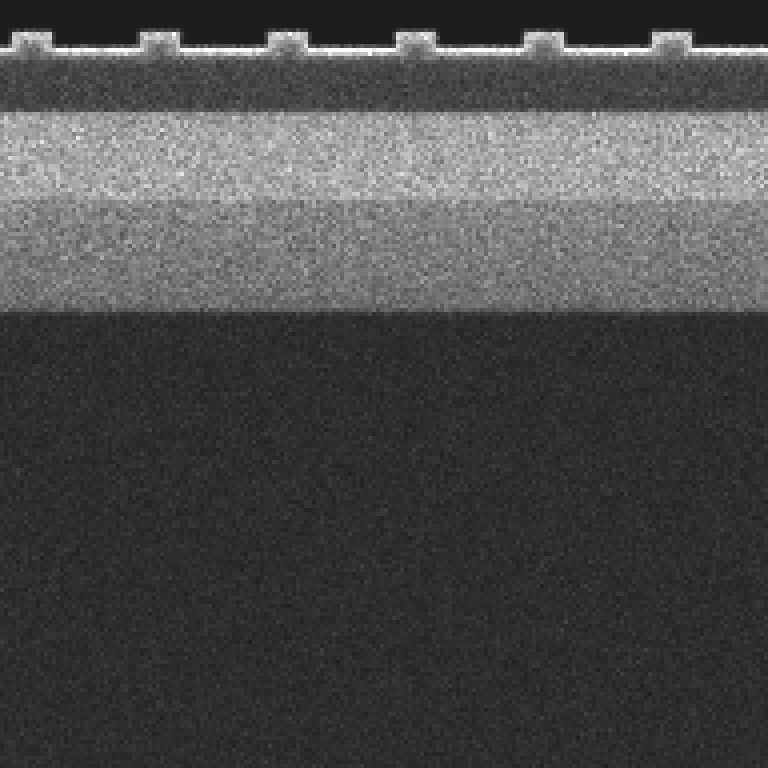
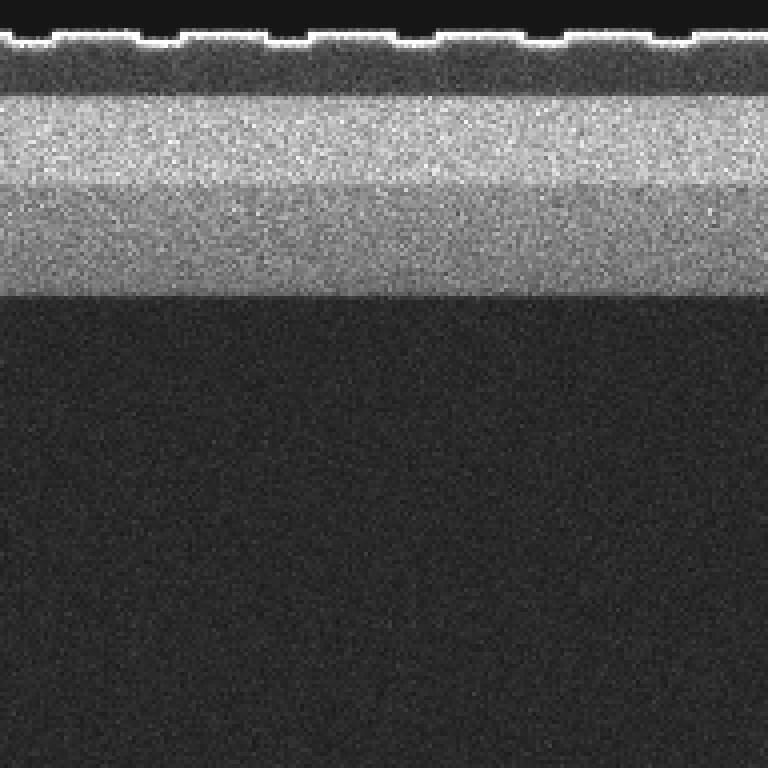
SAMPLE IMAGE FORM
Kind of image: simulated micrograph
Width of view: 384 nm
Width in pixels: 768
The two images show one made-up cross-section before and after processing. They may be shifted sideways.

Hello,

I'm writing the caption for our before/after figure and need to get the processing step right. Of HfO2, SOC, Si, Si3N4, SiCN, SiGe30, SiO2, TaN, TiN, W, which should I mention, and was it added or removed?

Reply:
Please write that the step removed SOC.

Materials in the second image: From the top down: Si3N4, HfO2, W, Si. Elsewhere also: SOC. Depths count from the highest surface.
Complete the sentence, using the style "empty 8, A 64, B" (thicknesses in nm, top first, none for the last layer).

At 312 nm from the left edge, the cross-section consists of Si3N4 32, HfO2 44, W 56, Si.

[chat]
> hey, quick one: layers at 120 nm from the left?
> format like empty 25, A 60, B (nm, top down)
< Si3N4 32, HfO2 44, W 56, Si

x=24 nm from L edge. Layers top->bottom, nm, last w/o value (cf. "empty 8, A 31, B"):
empty 4, Si3N4 28, HfO2 44, W 56, Si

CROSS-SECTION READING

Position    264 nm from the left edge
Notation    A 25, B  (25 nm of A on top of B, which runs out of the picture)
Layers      empty 4, Si3N4 28, HfO2 44, W 56, Si